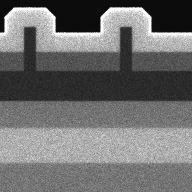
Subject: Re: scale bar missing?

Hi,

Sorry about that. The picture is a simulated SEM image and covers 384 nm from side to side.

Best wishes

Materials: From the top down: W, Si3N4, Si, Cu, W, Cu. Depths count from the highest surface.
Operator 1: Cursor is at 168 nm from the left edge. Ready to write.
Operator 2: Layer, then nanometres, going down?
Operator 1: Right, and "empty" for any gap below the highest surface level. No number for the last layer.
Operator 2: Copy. empty 50, W 38, Si3N4 38, Si 60, Cu 54, W 70, Cu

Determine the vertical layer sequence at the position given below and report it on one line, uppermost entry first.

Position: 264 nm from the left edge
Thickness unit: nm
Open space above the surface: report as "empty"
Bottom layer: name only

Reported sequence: W 88, Si3N4 38, Si 60, Cu 54, W 70, Cu